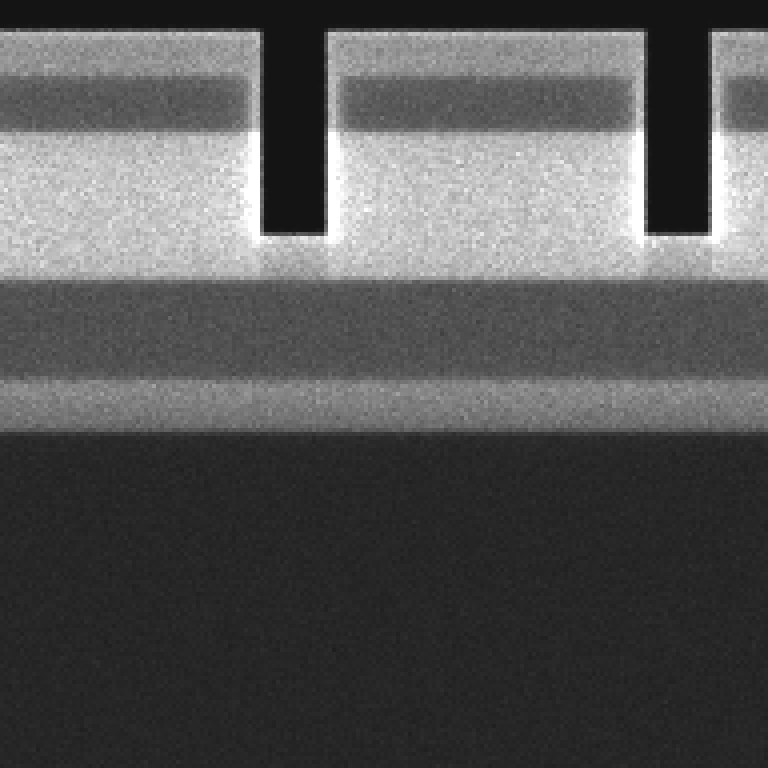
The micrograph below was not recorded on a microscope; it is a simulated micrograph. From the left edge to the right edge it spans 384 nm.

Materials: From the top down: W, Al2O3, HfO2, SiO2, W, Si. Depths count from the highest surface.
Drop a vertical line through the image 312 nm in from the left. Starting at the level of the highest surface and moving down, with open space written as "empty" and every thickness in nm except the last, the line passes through W 22, Al2O3 28, HfO2 74, SiO2 50, W 26, Si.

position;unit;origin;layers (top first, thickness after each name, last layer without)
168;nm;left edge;W 22, Al2O3 28, HfO2 74, SiO2 50, W 26, Si